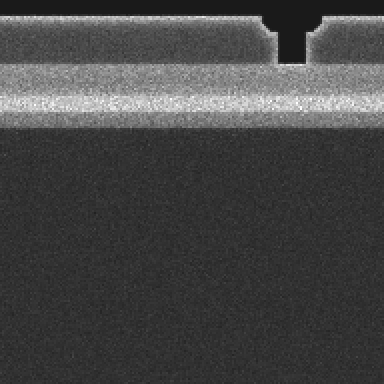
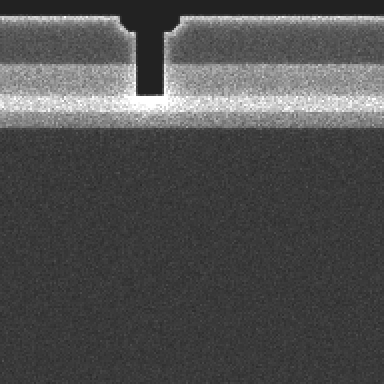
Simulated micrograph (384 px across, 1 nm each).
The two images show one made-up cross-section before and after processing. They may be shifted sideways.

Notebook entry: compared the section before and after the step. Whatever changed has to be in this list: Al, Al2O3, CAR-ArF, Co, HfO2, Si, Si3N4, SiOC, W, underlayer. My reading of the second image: W removed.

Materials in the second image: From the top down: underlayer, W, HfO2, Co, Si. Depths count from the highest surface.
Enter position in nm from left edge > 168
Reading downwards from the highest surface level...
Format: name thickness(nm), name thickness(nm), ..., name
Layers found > empty 16, underlayer 32, W 32, HfO2 16, Co 16, Si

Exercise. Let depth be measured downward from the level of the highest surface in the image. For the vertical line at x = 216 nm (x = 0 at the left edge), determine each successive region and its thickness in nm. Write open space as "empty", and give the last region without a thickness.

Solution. underlayer 48, W 32, HfO2 16, Co 16, Si